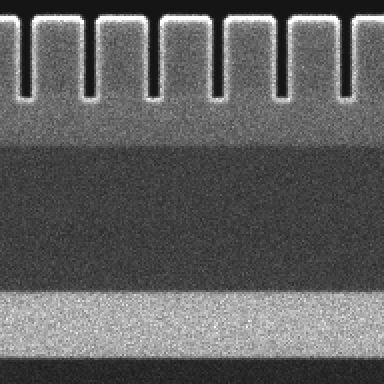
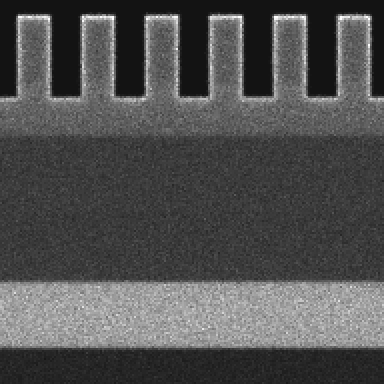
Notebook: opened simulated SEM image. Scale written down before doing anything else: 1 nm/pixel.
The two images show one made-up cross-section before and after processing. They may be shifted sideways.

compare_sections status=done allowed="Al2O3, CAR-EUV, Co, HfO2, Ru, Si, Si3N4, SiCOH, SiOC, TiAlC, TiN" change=removed material="Al2O3"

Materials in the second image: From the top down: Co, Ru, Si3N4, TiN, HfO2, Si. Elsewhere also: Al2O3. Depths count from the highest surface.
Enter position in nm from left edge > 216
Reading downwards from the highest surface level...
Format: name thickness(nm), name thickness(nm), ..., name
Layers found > Co 66, Ru 54, Si3N4 76, TiN 70, HfO2 66, Si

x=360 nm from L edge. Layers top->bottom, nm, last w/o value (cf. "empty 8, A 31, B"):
Co 66, Ru 54, Si3N4 76, TiN 70, HfO2 66, Si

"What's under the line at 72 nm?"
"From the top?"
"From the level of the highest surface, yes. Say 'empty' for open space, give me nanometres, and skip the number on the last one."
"empty 82, Ru 38, Si3N4 76, TiN 70, HfO2 66, Si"